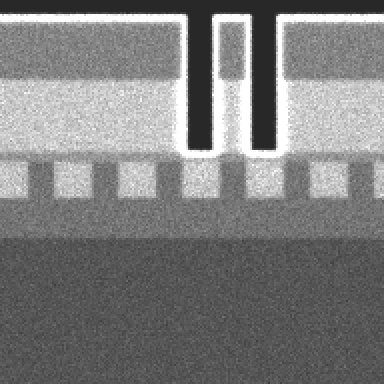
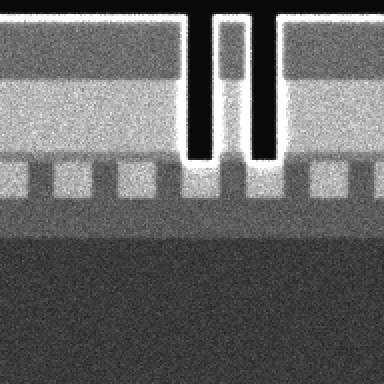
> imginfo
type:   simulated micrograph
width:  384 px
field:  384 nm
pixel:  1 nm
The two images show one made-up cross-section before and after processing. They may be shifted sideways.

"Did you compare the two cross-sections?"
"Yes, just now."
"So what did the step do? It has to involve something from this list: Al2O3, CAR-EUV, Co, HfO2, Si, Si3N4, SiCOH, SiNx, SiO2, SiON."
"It removed Si3N4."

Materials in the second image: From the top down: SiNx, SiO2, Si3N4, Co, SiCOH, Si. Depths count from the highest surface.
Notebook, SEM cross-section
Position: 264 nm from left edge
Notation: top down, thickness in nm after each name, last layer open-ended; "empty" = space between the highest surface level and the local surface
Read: empty 146, Co 36, SiCOH 40, Si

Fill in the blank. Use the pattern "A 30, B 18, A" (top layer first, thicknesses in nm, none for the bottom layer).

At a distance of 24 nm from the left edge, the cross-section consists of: SiNx 64, SiO2 72, Si3N4 10, Co 36, SiCOH 40, Si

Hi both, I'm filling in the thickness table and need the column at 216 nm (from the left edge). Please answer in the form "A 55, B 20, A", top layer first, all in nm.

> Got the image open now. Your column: SiNx 64, SiO2 72, Si3N4 10, Co 36, SiCOH 40, Si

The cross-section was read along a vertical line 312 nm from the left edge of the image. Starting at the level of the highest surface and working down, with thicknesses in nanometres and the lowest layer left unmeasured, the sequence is SiNx 64, SiO2 72, Si3N4 10, Co 36, SiCOH 40, Si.